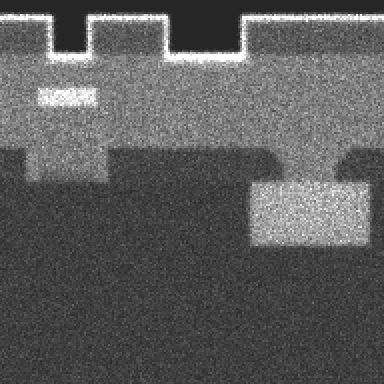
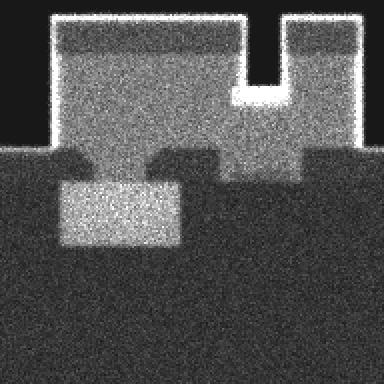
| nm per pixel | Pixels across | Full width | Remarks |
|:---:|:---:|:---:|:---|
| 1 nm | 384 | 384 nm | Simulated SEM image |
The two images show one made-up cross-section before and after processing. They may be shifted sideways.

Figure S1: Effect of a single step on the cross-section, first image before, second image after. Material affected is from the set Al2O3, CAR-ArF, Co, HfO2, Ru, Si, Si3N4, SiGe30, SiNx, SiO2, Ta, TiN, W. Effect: removed SiO2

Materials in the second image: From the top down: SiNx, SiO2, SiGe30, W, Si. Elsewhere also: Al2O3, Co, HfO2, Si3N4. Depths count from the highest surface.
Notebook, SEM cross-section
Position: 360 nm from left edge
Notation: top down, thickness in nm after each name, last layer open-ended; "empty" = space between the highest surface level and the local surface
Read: SiNx 38, SiO2 94, SiGe30 34, Si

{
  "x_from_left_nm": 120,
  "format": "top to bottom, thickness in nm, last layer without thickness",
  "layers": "SiNx 38, SiO2 128, W 64, Si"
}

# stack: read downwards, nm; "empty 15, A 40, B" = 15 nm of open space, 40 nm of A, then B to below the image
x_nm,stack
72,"SiNx 38, SiO2 94, SiGe30 34, W 64, Si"